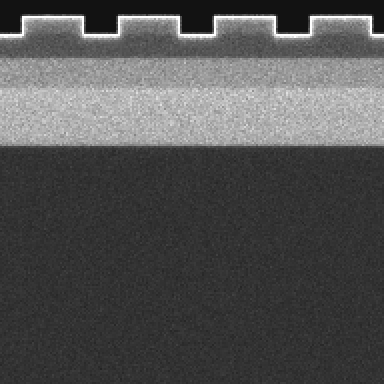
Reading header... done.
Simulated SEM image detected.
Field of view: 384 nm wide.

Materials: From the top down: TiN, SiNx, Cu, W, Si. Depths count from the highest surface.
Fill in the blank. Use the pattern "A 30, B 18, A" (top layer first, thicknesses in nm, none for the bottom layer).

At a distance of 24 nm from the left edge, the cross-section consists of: TiN 18, SiNx 24, Cu 30, W 58, Si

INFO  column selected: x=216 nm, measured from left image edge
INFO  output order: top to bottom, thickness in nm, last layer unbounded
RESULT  TiN 18, SiNx 24, Cu 30, W 58, Si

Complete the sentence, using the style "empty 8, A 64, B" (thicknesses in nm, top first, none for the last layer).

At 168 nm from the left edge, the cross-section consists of TiN 18, SiNx 24, Cu 30, W 58, Si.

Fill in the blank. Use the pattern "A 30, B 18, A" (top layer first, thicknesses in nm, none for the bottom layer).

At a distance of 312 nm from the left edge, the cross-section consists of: TiN 18, SiNx 24, Cu 30, W 58, Si